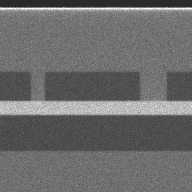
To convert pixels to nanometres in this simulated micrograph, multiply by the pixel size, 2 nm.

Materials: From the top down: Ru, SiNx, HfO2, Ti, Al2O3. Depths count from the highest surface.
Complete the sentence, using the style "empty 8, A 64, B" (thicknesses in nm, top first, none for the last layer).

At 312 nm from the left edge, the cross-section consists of Ru 186, HfO2 28, Ti 72, Al2O3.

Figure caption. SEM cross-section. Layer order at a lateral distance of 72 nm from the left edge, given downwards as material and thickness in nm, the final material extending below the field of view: Ru 186, HfO2 28, Ti 72, Al2O3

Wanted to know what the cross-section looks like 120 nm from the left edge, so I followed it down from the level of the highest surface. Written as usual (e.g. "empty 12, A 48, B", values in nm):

Ru 128, SiNx 58, HfO2 28, Ti 72, Al2O3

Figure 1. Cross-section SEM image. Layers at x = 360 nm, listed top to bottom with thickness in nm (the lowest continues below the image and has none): Ru 128, SiNx 58, HfO2 28, Ti 72, Al2O3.